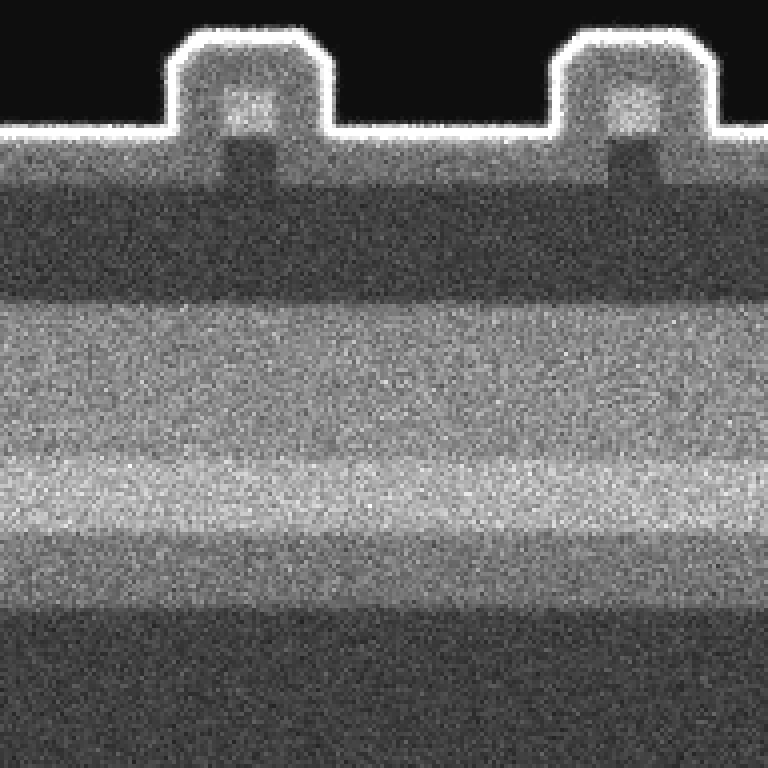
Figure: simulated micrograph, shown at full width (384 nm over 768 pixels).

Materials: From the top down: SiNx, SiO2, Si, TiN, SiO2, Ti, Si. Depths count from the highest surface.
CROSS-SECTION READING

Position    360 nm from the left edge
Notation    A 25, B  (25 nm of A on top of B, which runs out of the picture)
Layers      empty 48, SiNx 28, Si 60, TiN 78, SiO2 36, Ti 38, Si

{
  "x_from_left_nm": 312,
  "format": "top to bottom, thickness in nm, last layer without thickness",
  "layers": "SiNx 28, SiO2 24, Si 84, TiN 78, SiO2 36, Ti 38, Si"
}